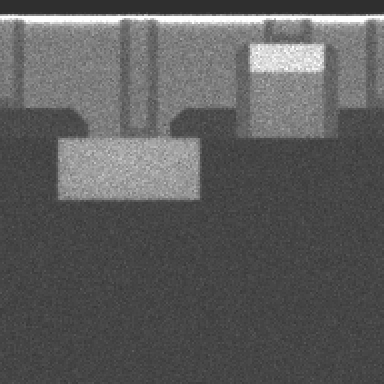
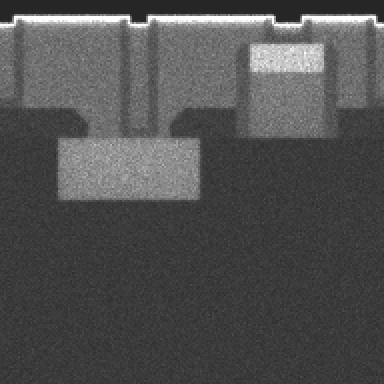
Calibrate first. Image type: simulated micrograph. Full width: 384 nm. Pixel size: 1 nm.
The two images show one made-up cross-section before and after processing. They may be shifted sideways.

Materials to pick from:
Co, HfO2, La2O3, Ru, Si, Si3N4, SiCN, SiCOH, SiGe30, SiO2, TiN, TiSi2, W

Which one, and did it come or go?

Co - removed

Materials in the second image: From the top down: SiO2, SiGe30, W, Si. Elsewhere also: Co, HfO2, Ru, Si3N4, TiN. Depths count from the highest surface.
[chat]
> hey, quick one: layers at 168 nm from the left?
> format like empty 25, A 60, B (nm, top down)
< SiO2 122, W 62, Si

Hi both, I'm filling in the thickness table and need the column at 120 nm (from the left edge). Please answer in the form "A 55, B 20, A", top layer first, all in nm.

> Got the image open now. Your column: TiN 122, W 62, Si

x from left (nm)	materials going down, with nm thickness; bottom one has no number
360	SiO2 92, SiGe30 30, Si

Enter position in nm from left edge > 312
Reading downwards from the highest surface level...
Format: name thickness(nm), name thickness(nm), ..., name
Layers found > SiO2 28, HfO2 28, Ru 66, Si